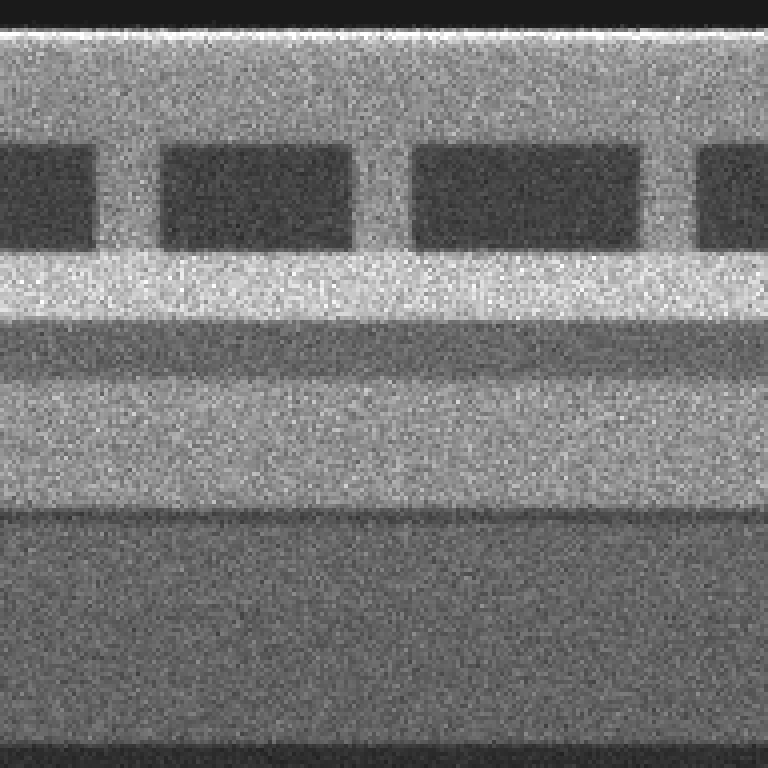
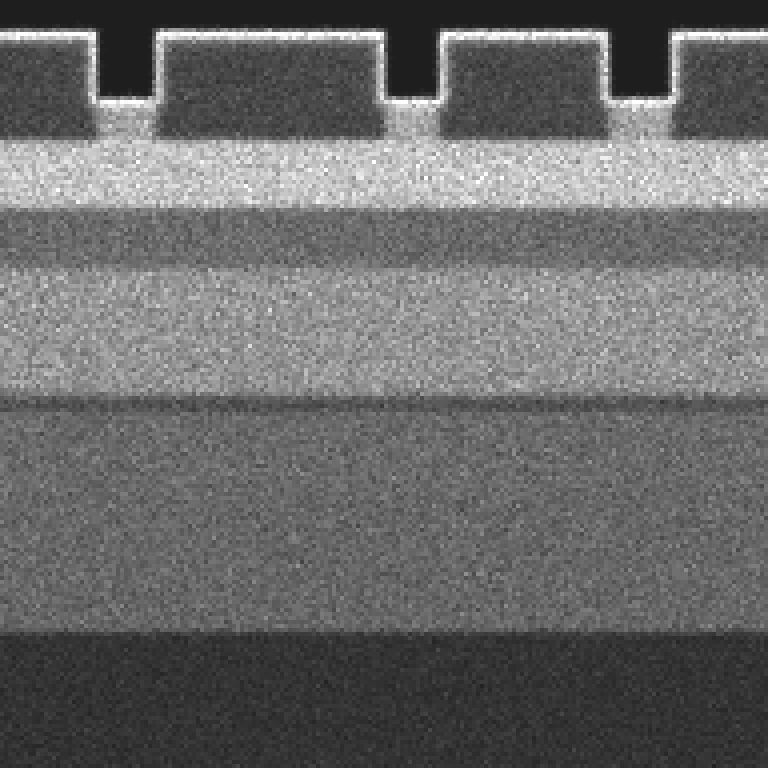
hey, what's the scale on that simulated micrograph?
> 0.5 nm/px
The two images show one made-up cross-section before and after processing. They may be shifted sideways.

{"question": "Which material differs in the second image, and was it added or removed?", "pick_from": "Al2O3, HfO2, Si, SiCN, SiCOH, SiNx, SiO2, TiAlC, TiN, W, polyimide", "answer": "W, removed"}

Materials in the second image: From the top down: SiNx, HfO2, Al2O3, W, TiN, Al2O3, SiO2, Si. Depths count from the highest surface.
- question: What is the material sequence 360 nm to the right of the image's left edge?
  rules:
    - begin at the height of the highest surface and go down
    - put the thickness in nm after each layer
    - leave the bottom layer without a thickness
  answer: SiNx 54, HfO2 34, Al2O3 30, W 64, TiN 8, Al2O3 40, SiO2 70, Si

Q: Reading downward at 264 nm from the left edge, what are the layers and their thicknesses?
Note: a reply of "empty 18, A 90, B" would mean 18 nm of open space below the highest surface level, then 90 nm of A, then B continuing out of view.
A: SiNx 54, HfO2 34, Al2O3 30, W 64, TiN 8, Al2O3 40, SiO2 70, Si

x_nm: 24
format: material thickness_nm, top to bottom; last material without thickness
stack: SiNx 54, HfO2 34, Al2O3 30, W 64, TiN 8, Al2O3 40, SiO2 70, Si